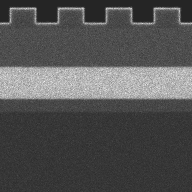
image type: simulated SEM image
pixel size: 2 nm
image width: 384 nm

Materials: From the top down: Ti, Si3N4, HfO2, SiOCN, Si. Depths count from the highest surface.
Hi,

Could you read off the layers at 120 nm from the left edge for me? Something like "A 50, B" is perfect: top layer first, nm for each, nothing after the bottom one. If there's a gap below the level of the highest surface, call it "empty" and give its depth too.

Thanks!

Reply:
Ti 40, Si3N4 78, HfO2 64, SiOCN 26, Si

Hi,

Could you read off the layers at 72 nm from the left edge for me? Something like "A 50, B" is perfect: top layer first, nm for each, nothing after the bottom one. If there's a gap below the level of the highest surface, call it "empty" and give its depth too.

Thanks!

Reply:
empty 30, Ti 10, Si3N4 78, HfO2 64, SiOCN 26, Si